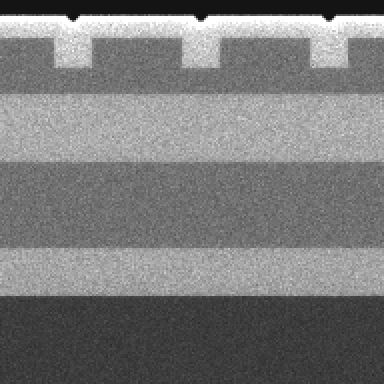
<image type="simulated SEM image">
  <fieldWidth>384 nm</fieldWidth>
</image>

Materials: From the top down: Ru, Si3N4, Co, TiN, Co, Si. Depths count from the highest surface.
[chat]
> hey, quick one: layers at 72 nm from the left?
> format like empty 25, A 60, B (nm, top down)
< empty 6, Ru 46, Si3N4 26, Co 68, TiN 86, Co 48, Si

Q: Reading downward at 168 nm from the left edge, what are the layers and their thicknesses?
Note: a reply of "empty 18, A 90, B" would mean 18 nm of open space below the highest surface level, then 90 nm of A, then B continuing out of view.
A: Ru 22, Si3N4 56, Co 68, TiN 86, Co 48, Si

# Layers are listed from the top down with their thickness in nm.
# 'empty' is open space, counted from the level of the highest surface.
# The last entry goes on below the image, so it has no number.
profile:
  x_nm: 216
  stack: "Ru 52, Si3N4 26, Co 68, TiN 86, Co 48, Si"